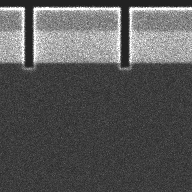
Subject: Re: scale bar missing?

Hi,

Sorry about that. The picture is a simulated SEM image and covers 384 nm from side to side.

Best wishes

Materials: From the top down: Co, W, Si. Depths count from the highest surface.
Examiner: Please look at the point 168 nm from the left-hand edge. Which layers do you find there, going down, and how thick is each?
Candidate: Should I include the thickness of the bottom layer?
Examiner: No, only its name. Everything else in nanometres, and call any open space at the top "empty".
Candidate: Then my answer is Co 46, W 64, Si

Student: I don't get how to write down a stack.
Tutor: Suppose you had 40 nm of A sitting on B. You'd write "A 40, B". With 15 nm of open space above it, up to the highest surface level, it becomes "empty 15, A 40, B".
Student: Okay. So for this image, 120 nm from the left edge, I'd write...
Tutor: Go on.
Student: Co 46, W 64, Si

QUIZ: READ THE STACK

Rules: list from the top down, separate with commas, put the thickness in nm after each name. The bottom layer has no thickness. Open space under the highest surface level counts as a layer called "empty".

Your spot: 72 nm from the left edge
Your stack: Co 46, W 64, Si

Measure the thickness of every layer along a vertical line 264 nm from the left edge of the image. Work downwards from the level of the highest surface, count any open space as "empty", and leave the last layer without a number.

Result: Co 46, W 64, Si